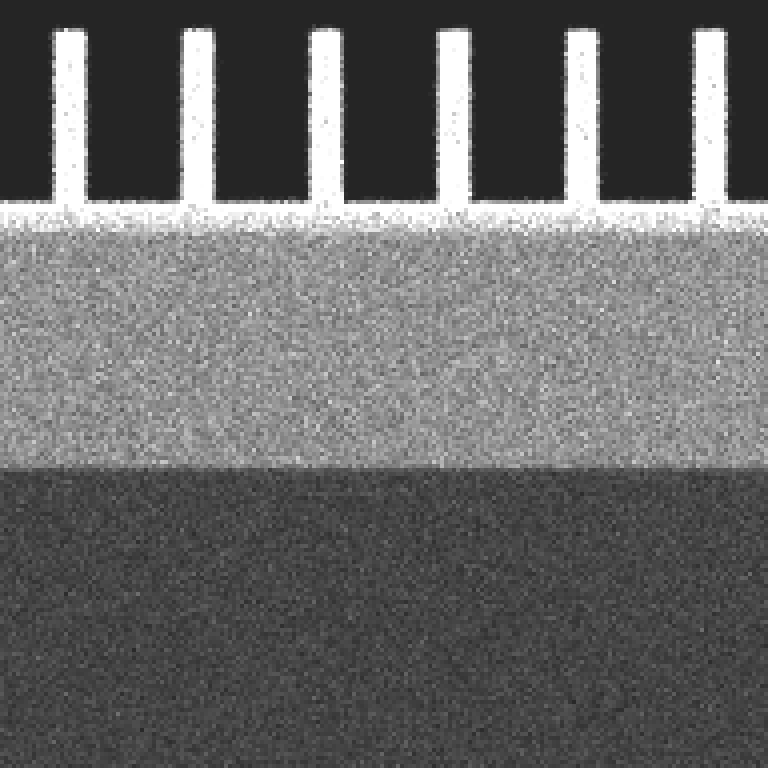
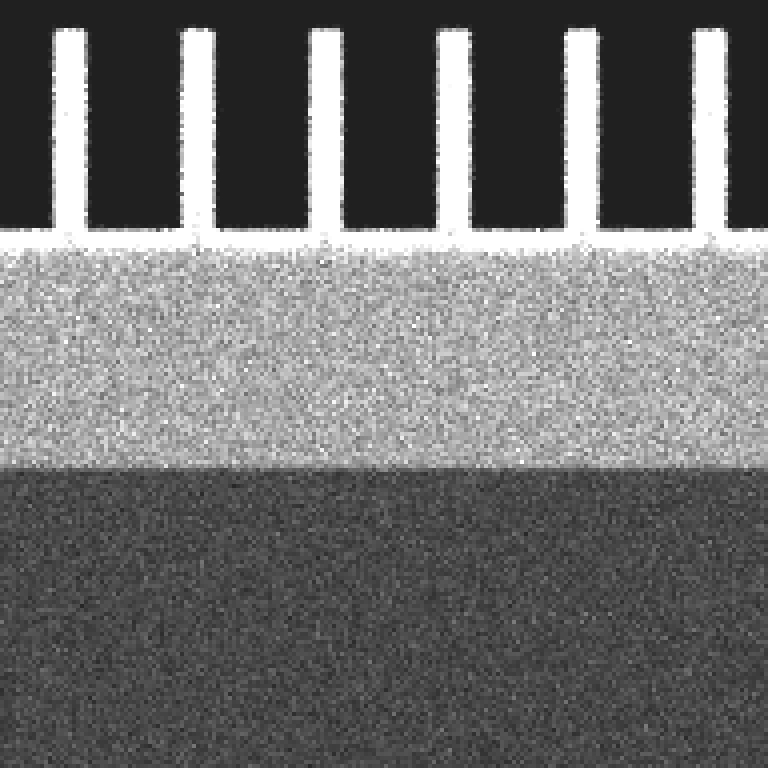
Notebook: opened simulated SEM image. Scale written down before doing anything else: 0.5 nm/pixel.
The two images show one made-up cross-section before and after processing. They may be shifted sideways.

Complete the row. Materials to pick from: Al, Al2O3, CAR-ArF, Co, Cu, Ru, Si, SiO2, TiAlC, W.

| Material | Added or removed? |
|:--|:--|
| Ru | removed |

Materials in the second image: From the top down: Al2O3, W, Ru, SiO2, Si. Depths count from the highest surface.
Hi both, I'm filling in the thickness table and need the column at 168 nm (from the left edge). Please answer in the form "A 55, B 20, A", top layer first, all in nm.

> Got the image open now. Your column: Al2O3 24, W 62, Ru 14, SiO2 118, Si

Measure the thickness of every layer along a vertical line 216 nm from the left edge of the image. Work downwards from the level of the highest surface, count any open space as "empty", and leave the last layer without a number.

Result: empty 100, SiO2 118, Si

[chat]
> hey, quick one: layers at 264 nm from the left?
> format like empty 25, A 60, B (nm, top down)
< empty 100, SiO2 118, Si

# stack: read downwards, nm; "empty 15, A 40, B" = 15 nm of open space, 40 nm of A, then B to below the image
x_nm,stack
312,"empty 100, SiO2 118, Si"